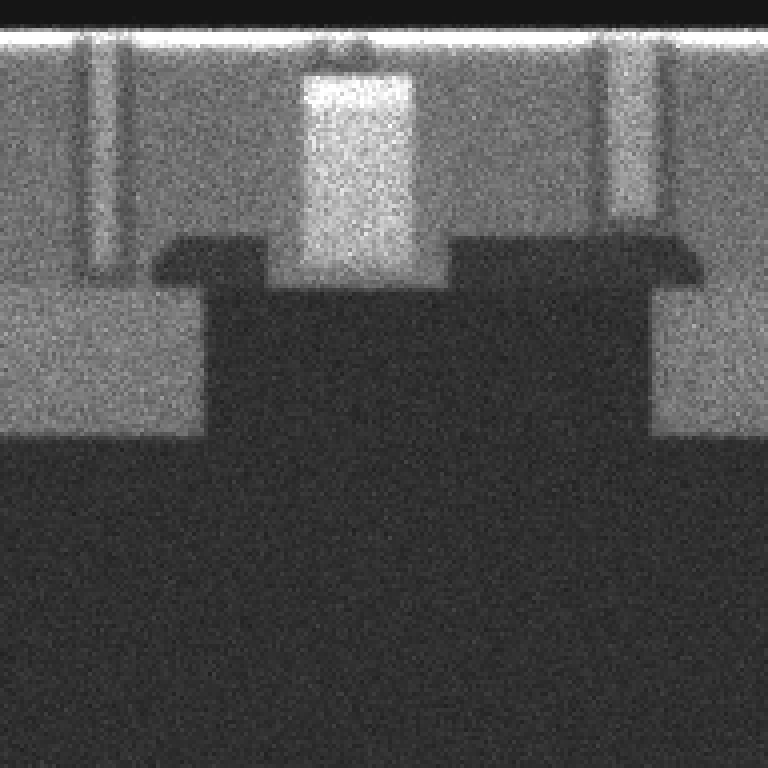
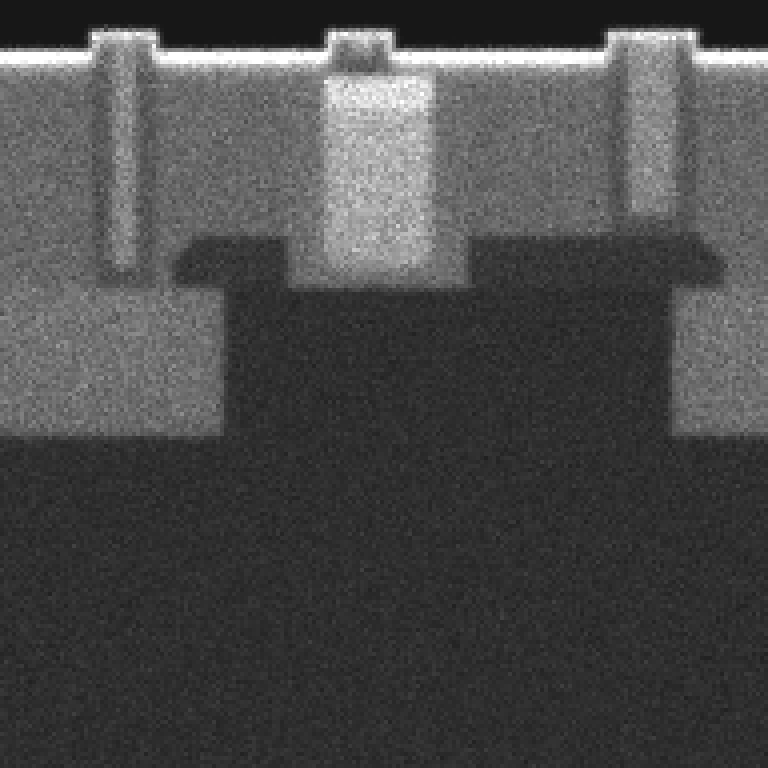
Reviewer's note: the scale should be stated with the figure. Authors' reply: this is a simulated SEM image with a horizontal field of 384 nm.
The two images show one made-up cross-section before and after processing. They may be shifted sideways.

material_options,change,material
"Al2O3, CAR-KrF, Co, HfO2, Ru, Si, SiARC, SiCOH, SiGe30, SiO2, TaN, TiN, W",removed,SiO2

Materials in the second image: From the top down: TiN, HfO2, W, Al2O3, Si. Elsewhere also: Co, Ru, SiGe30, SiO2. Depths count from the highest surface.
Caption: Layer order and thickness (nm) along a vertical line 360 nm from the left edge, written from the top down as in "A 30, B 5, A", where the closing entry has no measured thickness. empty 10, SiO2 104, SiGe30 14, Co 74, Si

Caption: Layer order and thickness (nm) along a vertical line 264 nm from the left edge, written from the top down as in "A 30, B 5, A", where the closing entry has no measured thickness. empty 10, SiO2 92, SiGe30 26, Si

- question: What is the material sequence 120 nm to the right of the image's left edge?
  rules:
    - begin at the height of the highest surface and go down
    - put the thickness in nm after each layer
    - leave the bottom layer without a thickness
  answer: empty 10, SiO2 92, SiGe30 26, Si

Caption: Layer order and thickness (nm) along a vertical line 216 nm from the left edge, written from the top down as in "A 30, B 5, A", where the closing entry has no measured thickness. empty 10, SiO2 12, Al2O3 106, Si